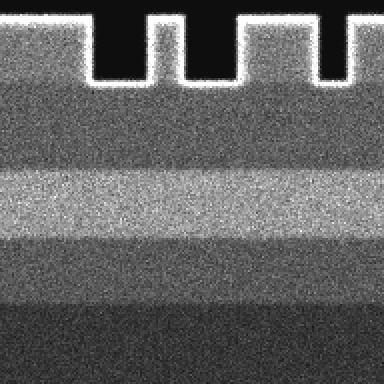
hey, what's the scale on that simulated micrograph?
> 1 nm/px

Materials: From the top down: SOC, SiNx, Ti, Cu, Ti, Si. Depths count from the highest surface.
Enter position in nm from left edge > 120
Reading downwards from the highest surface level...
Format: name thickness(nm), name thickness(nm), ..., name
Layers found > empty 66, SiNx 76, Ti 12, Cu 68, Ti 66, Si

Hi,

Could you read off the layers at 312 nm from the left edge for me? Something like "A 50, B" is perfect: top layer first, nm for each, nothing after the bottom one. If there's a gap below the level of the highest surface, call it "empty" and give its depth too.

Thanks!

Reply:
SOC 66, SiNx 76, Ti 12, Cu 68, Ti 66, Si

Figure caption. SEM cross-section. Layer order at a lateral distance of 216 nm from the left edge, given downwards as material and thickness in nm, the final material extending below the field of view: empty 66, SiNx 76, Ti 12, Cu 68, Ti 66, Si